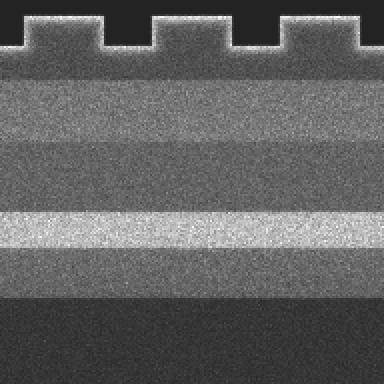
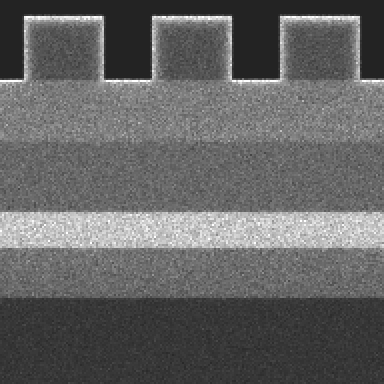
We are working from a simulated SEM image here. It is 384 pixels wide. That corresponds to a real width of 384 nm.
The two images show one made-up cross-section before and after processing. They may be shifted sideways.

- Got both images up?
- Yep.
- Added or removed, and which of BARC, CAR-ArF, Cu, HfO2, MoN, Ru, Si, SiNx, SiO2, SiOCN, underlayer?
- removed, underlayer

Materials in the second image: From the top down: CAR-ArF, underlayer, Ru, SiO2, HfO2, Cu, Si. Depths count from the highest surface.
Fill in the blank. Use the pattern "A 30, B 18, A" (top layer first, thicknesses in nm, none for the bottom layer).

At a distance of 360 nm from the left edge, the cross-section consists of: empty 64, Ru 62, SiO2 70, HfO2 36, Cu 50, Si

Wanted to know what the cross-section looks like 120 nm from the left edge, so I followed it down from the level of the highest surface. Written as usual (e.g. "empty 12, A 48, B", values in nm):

empty 64, Ru 62, SiO2 70, HfO2 36, Cu 50, Si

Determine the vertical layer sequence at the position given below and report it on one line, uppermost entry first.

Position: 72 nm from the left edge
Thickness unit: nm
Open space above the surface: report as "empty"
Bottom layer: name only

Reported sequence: CAR-ArF 30, underlayer 34, Ru 62, SiO2 70, HfO2 36, Cu 50, Si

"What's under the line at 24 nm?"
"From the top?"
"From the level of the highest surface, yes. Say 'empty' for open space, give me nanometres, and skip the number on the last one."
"CAR-ArF 30, underlayer 34, Ru 62, SiO2 70, HfO2 36, Cu 50, Si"